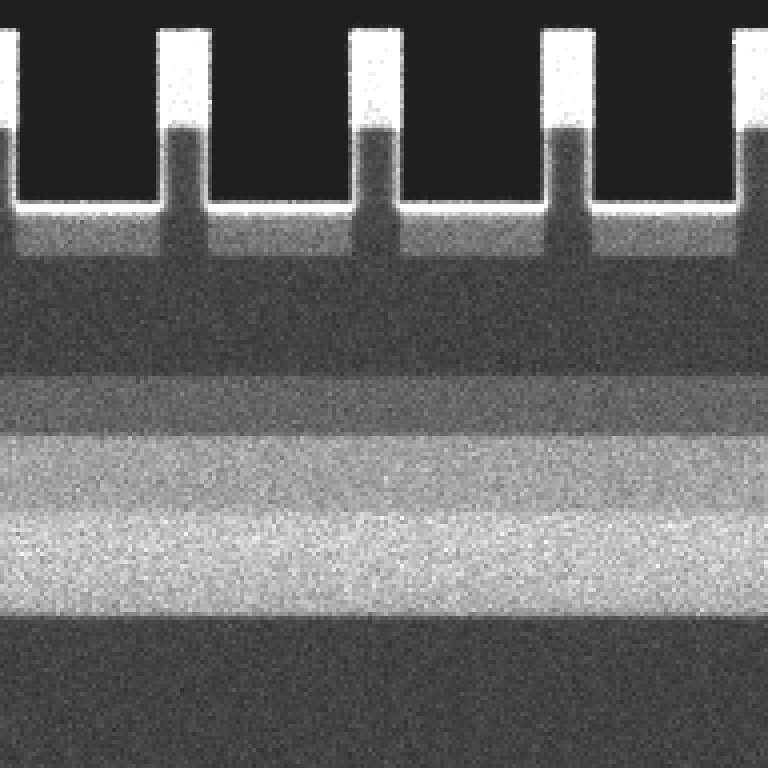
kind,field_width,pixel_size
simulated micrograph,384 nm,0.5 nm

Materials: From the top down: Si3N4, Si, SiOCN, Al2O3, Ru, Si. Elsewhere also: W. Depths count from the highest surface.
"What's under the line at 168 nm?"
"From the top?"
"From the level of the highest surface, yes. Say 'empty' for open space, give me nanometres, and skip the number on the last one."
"empty 86, Si3N4 26, Si 60, SiOCN 30, Al2O3 38, Ru 52, Si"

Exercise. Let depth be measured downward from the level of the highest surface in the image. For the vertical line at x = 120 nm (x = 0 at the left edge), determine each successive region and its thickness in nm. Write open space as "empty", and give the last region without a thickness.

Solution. empty 86, Si3N4 26, Si 60, SiOCN 30, Al2O3 38, Ru 52, Si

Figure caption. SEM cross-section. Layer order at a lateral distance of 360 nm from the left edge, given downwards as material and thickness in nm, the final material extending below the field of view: empty 86, Si3N4 26, Si 60, SiOCN 30, Al2O3 38, Ru 52, Si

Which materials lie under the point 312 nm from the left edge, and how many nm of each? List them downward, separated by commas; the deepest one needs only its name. empty 86, Si3N4 26, Si 60, SiOCN 30, Al2O3 38, Ru 52, Si